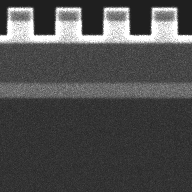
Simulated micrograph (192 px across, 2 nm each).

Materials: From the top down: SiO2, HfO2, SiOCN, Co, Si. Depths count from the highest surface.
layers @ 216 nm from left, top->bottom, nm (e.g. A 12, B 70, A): SiO2 26, HfO2 44, SiOCN 80, Co 30, Si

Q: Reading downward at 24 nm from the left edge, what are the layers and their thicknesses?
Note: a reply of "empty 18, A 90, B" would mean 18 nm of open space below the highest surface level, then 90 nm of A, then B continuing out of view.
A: SiO2 26, HfO2 44, SiOCN 80, Co 30, Si